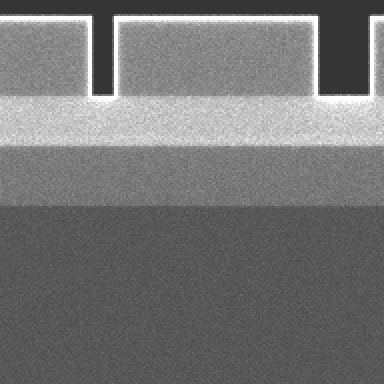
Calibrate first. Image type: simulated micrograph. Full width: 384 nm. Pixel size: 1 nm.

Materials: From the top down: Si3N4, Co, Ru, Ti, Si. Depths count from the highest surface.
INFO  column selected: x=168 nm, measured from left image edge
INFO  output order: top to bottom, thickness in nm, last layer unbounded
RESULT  Si3N4 80, Co 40, Ru 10, Ti 60, Si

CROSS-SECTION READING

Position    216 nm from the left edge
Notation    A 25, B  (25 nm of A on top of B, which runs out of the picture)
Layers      Si3N4 80, Co 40, Ru 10, Ti 60, Si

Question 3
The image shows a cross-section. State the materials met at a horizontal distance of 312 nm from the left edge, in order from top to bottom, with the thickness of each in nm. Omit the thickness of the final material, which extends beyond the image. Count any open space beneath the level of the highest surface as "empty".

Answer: Si3N4 80, Co 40, Ru 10, Ti 60, Si